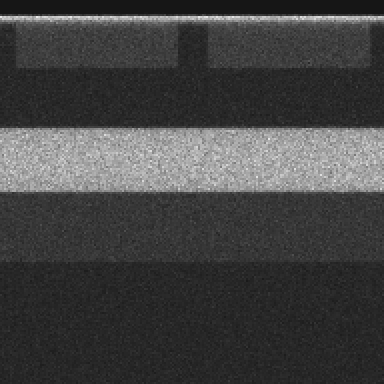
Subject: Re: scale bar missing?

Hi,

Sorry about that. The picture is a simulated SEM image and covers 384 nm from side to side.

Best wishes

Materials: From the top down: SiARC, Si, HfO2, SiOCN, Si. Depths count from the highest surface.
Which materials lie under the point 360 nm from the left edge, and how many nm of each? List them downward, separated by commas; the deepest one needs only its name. SiARC 52, Si 60, HfO2 64, SiOCN 70, Si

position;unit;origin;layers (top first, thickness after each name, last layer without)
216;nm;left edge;SiARC 52, Si 60, HfO2 64, SiOCN 70, Si